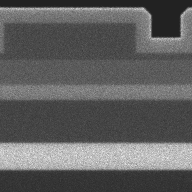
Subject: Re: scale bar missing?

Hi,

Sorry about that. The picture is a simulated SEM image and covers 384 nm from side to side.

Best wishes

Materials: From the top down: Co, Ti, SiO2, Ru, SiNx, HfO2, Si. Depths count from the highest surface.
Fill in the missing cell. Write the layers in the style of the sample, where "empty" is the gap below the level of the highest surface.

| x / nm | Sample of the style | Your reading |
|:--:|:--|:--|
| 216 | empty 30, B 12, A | Co 30, Ti 74, SiO2 50, Ru 30, SiNx 86, HfO2 54, Si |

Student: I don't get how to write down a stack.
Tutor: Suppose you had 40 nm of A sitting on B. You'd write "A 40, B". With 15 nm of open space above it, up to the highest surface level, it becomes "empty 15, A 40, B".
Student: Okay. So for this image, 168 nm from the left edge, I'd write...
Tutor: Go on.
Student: Co 30, Ti 74, SiO2 50, Ru 30, SiNx 86, HfO2 54, Si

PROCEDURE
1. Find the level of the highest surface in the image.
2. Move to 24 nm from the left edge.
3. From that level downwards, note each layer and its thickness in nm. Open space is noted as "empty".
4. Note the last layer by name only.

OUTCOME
Co 30, Ti 74, SiO2 50, Ru 30, SiNx 86, HfO2 54, Si